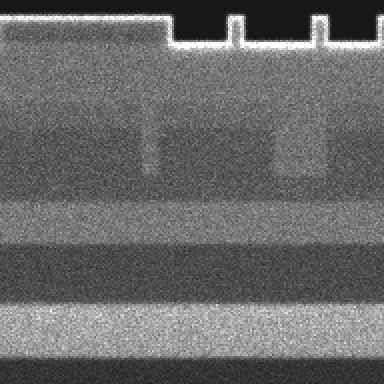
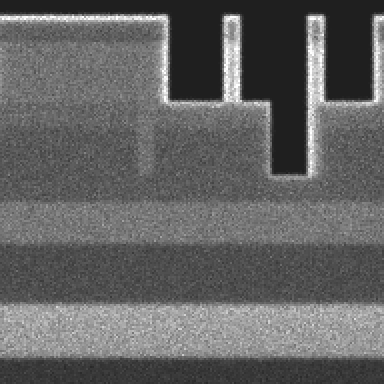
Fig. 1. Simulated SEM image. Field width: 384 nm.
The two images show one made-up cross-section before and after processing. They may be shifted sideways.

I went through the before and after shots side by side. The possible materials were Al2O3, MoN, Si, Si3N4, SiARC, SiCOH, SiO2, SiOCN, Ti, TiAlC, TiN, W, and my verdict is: removed, SiO2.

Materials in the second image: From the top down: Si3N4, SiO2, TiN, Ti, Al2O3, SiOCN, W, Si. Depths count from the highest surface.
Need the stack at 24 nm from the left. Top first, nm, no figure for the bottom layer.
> Si3N4 26, SiO2 60, TiN 26, Ti 74, Al2O3 42, SiOCN 60, W 54, Si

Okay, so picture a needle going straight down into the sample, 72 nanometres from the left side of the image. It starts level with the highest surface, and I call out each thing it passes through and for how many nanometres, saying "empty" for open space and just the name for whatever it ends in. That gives Si3N4 26, SiO2 60, TiN 26, Ti 74, Al2O3 42, SiOCN 60, W 54, Si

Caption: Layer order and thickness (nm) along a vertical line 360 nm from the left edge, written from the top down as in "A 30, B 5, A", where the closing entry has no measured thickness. empty 86, TiN 26, Ti 74, Al2O3 42, SiOCN 60, W 54, Si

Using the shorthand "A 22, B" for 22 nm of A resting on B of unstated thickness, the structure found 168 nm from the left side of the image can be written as empty 86, TiN 26, Ti 74, Al2O3 42, SiOCN 60, W 54, Si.